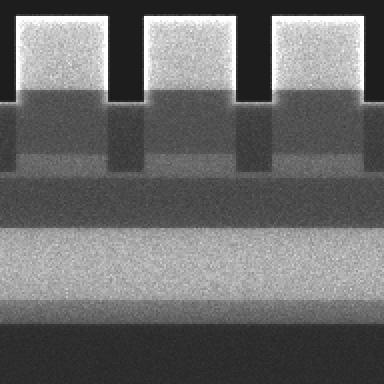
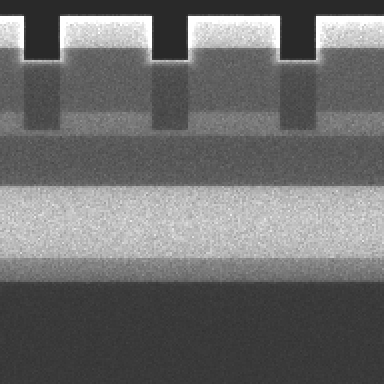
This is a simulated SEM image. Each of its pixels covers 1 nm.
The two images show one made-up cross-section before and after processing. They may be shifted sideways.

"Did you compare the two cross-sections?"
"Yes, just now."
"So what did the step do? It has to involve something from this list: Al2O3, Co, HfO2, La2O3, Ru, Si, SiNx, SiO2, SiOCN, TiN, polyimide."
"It removed HfO2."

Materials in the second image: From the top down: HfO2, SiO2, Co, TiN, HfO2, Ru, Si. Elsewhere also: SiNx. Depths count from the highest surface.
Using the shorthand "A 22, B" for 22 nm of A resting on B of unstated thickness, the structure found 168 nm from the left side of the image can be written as empty 44, SiNx 70, Co 6, TiN 50, HfO2 72, Ru 24, Si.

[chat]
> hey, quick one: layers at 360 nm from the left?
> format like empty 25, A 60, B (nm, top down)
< HfO2 32, SiO2 64, Co 24, TiN 50, HfO2 72, Ru 24, Si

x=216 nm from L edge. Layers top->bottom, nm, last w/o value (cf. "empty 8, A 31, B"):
HfO2 32, SiO2 64, Co 24, TiN 50, HfO2 72, Ru 24, Si